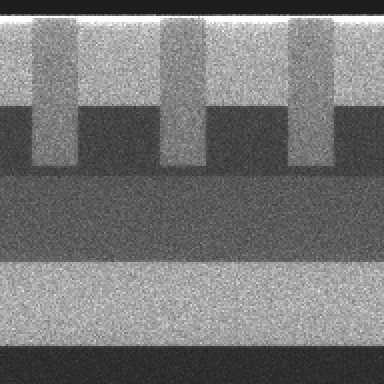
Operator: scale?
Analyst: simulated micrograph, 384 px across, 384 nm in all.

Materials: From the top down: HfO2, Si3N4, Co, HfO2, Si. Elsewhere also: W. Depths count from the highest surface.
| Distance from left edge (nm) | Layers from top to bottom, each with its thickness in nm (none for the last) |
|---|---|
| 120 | HfO2 90, Si3N4 70, Co 86, HfO2 84, Si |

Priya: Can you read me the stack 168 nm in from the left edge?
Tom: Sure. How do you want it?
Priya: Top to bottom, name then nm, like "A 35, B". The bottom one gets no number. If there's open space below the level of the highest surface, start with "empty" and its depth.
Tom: W 150, Si3N4 10, Co 86, HfO2 84, Si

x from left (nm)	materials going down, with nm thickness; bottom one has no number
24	HfO2 90, Si3N4 70, Co 86, HfO2 84, Si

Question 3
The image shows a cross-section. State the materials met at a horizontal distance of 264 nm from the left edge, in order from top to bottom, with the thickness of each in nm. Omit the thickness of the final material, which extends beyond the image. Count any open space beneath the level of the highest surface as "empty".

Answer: HfO2 90, Si3N4 70, Co 86, HfO2 84, Si